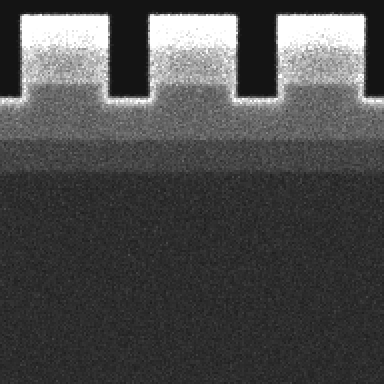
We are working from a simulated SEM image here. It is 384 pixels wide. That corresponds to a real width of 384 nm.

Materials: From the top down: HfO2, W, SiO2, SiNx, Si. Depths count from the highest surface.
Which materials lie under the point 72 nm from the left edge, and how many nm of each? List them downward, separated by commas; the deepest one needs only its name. HfO2 30, W 38, SiO2 56, SiNx 32, Si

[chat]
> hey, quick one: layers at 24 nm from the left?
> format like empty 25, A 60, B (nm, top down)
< HfO2 30, W 38, SiO2 56, SiNx 32, Si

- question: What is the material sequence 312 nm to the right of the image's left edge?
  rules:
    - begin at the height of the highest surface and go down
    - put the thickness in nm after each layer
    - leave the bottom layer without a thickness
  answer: HfO2 30, W 38, SiO2 56, SiNx 32, Si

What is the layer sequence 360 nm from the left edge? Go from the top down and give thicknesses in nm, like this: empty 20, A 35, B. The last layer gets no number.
HfO2 30, W 38, SiO2 56, SiNx 32, Si